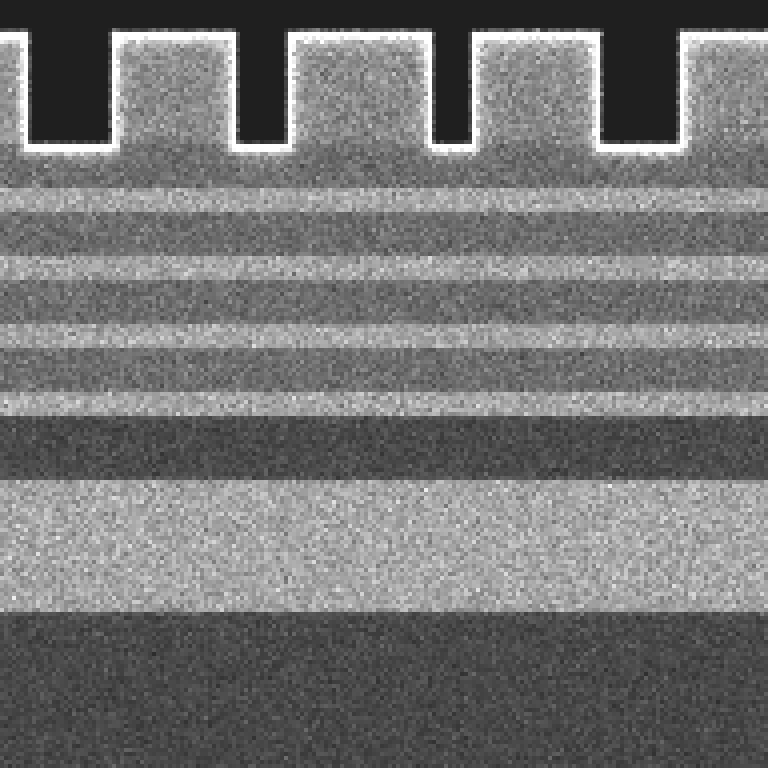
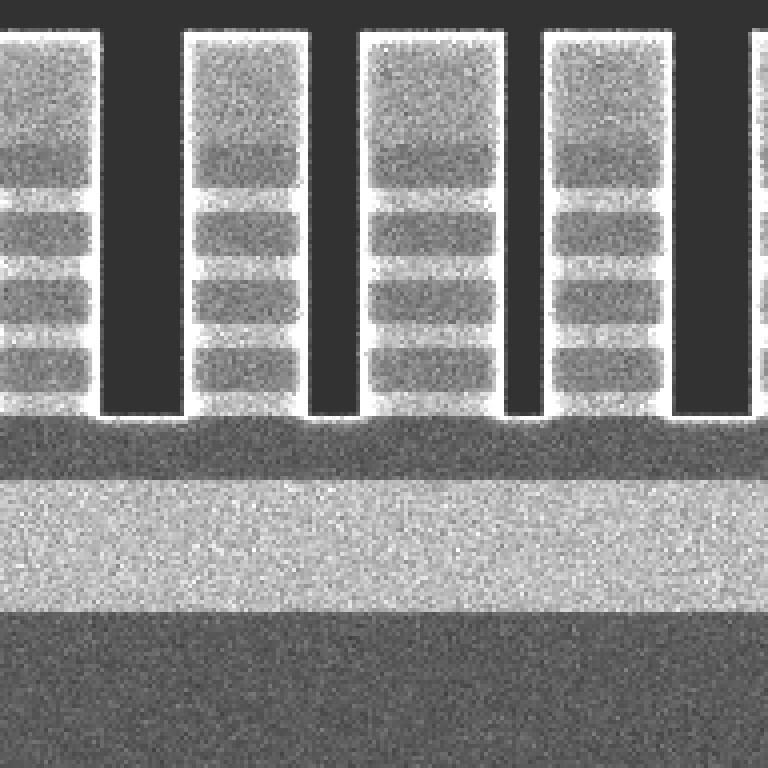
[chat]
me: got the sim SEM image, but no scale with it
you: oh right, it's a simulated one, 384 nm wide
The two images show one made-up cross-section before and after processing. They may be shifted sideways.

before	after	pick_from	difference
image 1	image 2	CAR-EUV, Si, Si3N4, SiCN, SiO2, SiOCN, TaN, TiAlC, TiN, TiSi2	SiO2 and SiOCN removed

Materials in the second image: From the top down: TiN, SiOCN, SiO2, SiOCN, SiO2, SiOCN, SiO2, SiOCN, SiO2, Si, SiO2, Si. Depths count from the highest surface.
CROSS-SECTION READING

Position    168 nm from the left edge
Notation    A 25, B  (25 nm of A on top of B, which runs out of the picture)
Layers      empty 192, Si 32, SiO2 66, Si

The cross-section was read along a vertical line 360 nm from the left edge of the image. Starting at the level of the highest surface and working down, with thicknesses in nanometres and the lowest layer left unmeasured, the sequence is empty 192, Si 32, SiO2 66, Si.